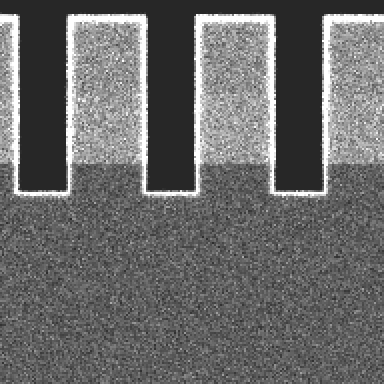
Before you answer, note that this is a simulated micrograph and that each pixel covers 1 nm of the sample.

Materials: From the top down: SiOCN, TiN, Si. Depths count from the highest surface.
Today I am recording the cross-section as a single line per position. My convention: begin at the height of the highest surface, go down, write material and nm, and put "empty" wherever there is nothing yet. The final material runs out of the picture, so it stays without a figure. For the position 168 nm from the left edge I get empty 176, Si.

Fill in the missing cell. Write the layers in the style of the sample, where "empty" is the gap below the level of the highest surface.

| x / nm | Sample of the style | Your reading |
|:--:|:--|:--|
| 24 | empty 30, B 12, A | empty 176, Si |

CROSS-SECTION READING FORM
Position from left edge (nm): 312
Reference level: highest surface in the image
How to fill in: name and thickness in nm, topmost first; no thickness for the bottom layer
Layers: empty 176, Si